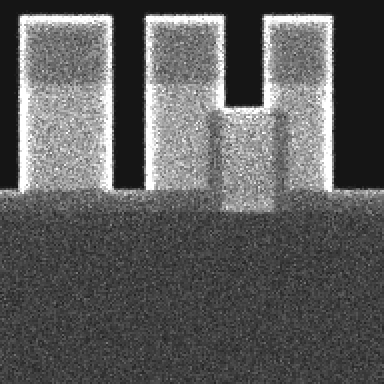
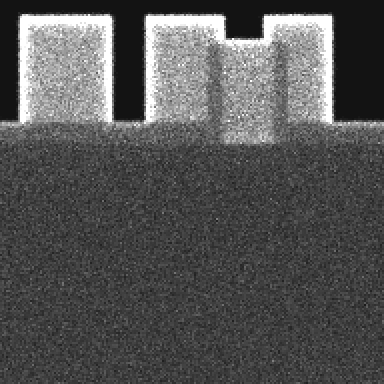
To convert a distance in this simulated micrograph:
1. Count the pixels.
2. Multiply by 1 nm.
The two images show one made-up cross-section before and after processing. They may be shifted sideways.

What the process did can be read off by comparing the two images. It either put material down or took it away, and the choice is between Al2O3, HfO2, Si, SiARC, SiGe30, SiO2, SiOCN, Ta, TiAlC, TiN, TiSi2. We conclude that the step removed SiARC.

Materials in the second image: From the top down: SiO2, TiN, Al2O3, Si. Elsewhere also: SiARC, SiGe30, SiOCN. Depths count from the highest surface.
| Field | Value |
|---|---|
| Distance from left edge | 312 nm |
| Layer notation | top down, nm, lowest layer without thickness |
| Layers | SiO2 106, SiGe30 22, Si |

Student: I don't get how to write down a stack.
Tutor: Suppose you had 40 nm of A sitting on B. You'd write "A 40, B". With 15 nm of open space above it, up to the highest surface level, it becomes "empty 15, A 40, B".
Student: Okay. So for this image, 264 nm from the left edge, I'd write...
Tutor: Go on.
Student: SiO2 24, TiN 92, Al2O3 12, Si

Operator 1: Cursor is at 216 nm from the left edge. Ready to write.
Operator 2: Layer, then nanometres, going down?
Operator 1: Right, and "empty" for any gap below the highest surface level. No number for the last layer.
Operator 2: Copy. SiO2 24, SiOCN 104, Si